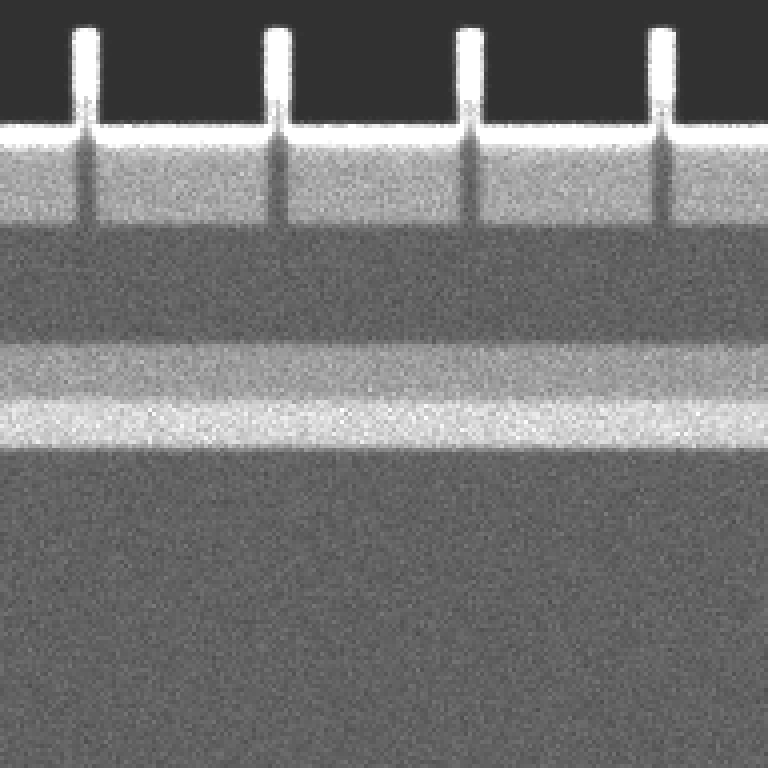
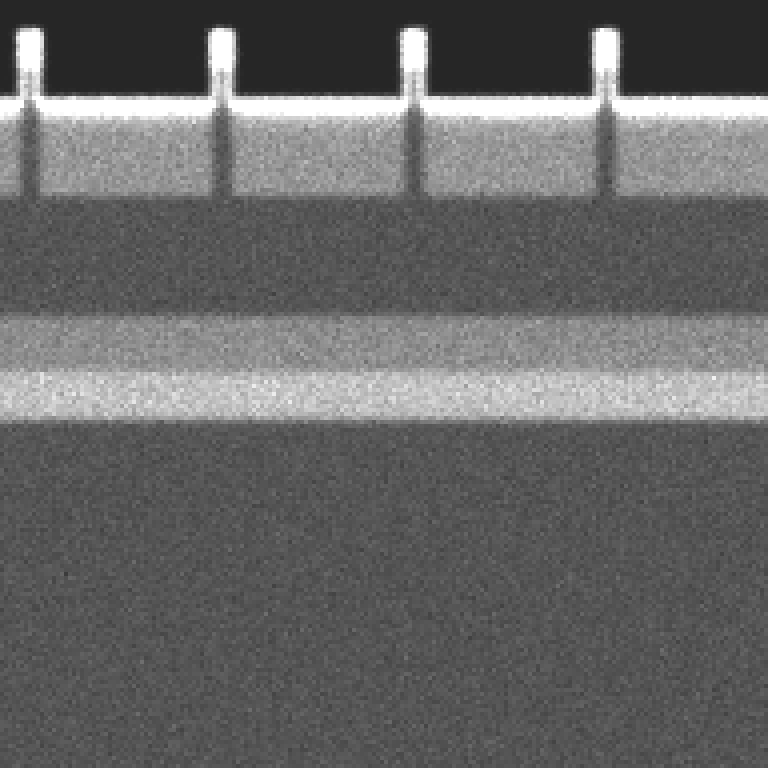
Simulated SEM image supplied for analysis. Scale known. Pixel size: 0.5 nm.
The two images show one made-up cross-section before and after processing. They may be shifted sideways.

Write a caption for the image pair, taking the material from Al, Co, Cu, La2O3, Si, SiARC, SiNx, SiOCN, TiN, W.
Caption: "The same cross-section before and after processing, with SiOCN removed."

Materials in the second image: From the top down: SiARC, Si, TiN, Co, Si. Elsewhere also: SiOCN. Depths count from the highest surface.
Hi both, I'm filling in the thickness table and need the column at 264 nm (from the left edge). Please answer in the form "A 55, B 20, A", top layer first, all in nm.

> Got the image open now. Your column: empty 34, SiARC 48, Si 60, TiN 28, Co 24, Si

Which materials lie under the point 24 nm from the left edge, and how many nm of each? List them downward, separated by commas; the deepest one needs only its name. empty 34, SiARC 48, Si 60, TiN 28, Co 24, Si